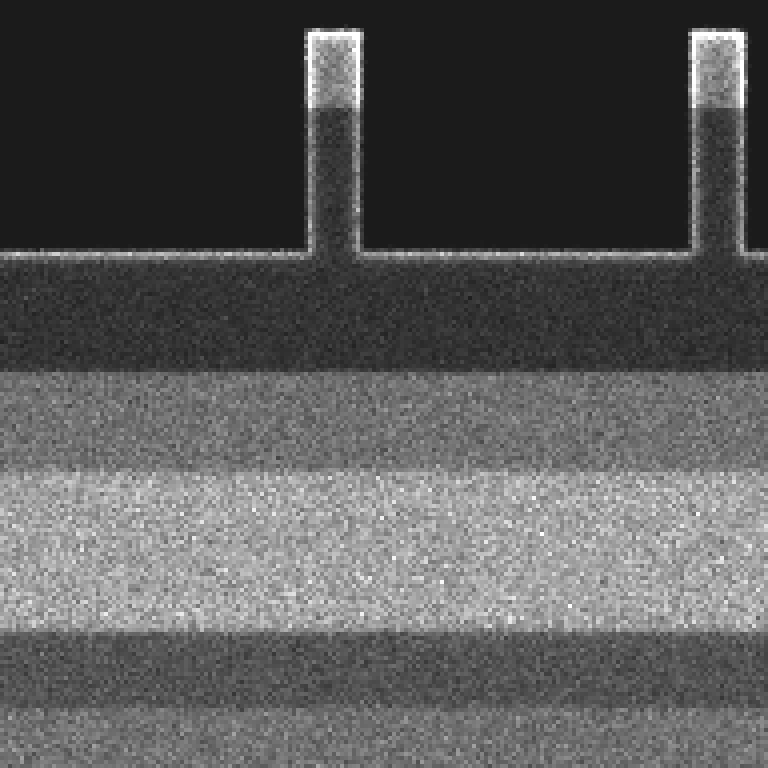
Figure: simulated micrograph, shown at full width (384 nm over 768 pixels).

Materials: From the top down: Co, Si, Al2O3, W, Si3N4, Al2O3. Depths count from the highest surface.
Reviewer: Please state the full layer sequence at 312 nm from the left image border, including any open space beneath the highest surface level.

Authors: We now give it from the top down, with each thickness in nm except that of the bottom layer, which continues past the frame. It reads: empty 110, Si 60, Al2O3 50, W 80, Si3N4 38, Al2O3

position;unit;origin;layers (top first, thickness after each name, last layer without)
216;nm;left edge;empty 110, Si 60, Al2O3 50, W 80, Si3N4 38, Al2O3